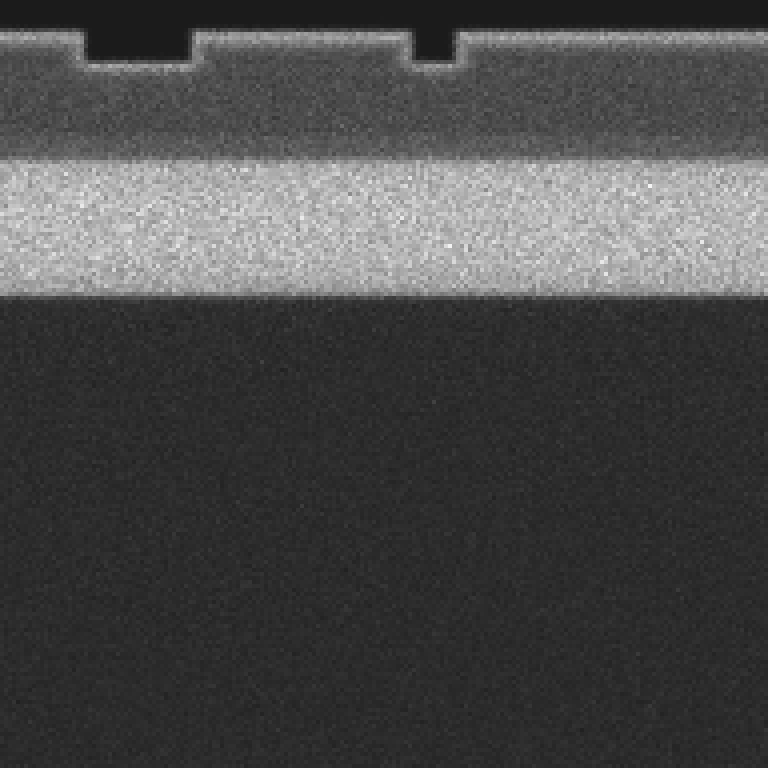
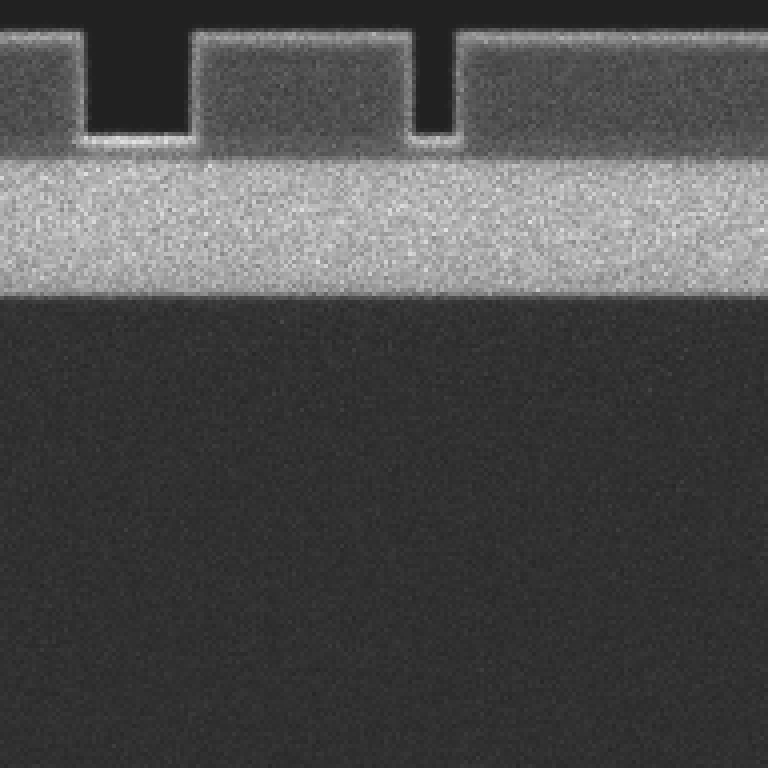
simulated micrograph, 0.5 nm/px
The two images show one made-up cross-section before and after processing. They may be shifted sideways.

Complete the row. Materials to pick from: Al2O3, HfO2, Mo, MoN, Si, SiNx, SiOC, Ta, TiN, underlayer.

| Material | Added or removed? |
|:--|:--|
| TiN | removed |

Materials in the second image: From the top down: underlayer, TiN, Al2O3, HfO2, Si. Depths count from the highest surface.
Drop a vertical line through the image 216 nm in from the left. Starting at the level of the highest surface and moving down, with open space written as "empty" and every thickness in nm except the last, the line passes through empty 52, Al2O3 12, HfO2 68, Si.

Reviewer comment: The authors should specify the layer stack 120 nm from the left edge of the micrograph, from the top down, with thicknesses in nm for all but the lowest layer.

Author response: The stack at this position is underlayer 16, TiN 36, Al2O3 12, HfO2 68, Si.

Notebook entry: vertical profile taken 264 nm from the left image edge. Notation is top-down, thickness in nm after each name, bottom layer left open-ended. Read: underlayer 16, TiN 36, Al2O3 12, HfO2 68, Si